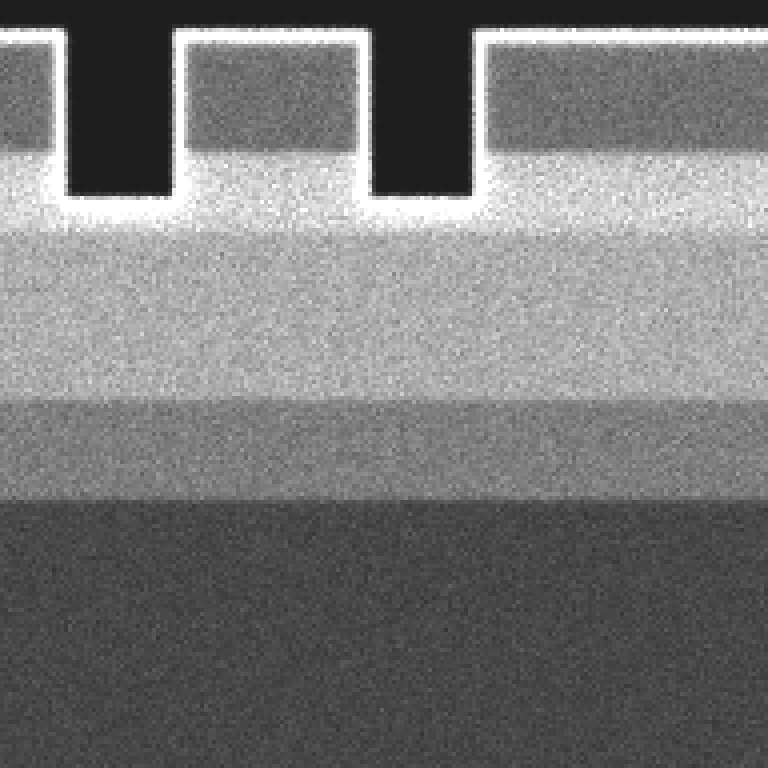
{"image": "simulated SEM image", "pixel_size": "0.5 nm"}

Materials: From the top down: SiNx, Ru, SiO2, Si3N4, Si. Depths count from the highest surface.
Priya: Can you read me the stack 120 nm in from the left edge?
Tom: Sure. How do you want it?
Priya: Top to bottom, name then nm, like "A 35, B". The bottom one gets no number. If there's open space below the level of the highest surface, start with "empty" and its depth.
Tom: SiNx 60, Ru 40, SiO2 84, Si3N4 50, Si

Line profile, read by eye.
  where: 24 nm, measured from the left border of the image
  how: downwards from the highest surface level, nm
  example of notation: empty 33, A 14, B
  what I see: SiNx 60, Ru 40, SiO2 84, Si3N4 50, Si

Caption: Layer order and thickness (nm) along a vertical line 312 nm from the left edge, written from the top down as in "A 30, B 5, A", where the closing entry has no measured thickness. SiNx 60, Ru 40, SiO2 84, Si3N4 50, Si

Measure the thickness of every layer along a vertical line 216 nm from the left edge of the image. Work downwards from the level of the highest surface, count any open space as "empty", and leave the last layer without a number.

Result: empty 84, Ru 16, SiO2 84, Si3N4 50, Si